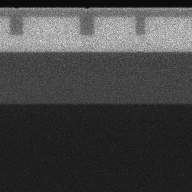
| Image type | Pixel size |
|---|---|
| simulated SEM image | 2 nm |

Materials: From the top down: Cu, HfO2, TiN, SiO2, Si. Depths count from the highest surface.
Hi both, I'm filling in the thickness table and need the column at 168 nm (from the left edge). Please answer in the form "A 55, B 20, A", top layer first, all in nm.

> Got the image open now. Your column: Cu 54, HfO2 34, TiN 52, SiO2 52, Si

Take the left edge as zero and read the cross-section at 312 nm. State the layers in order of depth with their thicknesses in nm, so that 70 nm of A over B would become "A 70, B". Cu 18, HfO2 70, TiN 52, SiO2 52, Si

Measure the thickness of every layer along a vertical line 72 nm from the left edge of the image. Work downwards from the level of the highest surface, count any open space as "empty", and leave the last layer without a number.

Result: Cu 18, HfO2 70, TiN 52, SiO2 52, Si